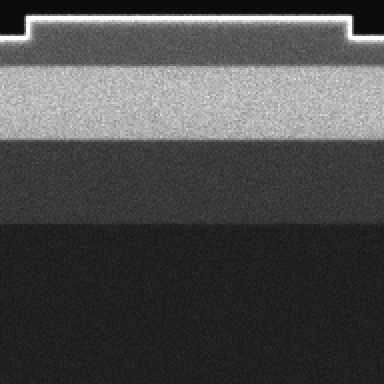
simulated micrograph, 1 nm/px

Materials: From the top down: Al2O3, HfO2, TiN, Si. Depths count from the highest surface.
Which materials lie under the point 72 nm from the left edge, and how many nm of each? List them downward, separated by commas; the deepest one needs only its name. Al2O3 50, HfO2 74, TiN 84, Si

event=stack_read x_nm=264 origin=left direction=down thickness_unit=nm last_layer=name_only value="Al2O3 50, HfO2 74, TiN 84, Si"